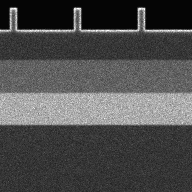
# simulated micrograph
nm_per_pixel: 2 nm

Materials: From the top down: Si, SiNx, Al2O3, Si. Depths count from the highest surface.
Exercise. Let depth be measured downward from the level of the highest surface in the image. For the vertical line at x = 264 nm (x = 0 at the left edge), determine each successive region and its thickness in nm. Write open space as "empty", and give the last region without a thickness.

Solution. empty 44, Si 60, SiNx 66, Al2O3 64, Si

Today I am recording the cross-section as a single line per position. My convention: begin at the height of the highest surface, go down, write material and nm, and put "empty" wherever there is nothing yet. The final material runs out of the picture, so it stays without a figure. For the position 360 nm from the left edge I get empty 44, Si 60, SiNx 66, Al2O3 64, Si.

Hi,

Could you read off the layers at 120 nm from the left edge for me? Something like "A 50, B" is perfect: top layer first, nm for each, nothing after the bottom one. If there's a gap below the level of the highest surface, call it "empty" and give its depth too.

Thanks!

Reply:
empty 44, Si 60, SiNx 66, Al2O3 64, Si